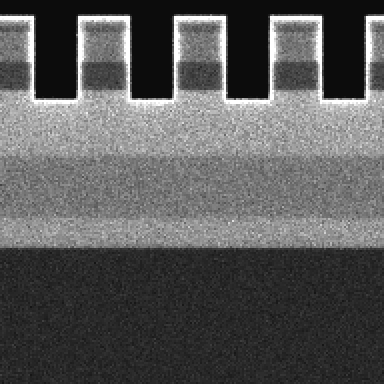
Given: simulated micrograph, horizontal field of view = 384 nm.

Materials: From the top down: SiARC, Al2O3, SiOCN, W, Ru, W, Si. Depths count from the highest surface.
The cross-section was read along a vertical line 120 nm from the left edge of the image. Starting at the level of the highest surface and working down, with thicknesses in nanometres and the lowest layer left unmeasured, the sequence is SiARC 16, Al2O3 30, SiOCN 28, W 66, Ru 62, W 30, Si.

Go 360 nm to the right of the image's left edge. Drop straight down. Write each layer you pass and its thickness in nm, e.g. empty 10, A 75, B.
empty 84, W 56, Ru 62, W 30, Si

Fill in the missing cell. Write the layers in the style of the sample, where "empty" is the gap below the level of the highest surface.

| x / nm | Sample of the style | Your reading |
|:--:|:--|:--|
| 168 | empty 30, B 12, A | empty 84, W 56, Ru 62, W 30, Si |